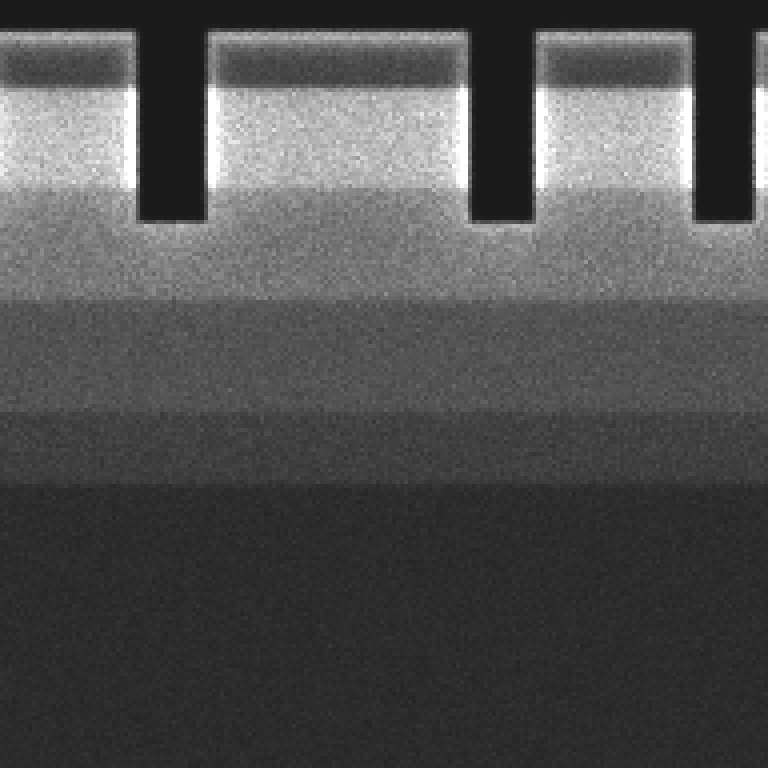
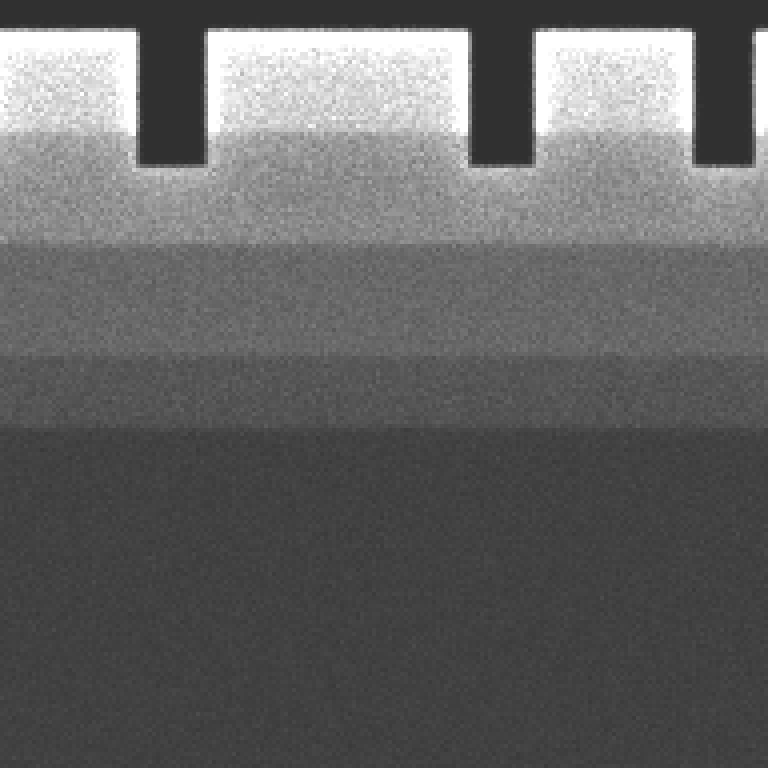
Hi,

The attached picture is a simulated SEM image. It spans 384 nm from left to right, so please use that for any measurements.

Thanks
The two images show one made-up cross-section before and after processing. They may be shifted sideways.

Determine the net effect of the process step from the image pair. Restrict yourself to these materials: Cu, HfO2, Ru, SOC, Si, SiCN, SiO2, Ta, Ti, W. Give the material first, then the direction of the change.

SOC: removed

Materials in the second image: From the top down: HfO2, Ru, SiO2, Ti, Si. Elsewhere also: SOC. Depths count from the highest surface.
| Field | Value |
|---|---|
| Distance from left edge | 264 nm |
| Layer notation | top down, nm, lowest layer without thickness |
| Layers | empty 68, Ru 38, SiO2 56, Ti 36, Si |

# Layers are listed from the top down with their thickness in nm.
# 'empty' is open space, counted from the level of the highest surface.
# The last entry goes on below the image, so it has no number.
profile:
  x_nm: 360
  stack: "empty 68, Ru 38, SiO2 56, Ti 36, Si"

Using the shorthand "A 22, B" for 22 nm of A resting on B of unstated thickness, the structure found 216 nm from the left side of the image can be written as HfO2 50, Ru 56, SiO2 56, Ti 36, Si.